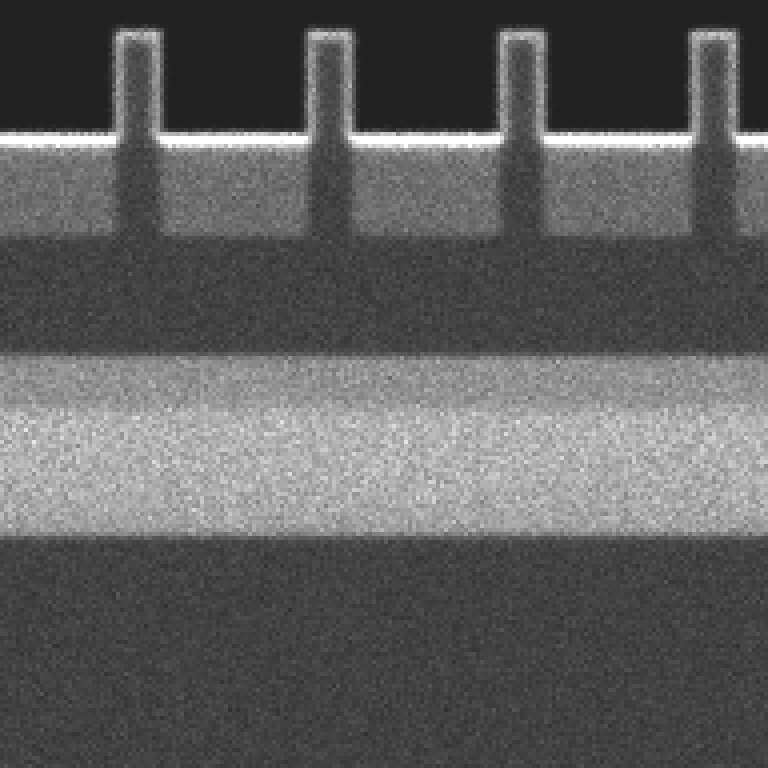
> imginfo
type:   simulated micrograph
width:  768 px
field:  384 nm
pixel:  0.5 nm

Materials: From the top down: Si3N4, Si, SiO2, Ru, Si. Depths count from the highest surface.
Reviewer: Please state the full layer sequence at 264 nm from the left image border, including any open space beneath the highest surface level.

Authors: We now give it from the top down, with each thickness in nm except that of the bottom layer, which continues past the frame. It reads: Si 162, SiO2 26, Ru 64, Si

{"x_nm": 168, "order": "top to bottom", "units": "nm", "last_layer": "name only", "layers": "Si 162, SiO2 26, Ru 64, Si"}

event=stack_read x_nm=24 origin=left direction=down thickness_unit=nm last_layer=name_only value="empty 52, Si3N4 50, Si 60, SiO2 26, Ru 64, Si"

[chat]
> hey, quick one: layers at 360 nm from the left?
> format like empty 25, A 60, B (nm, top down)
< Si 162, SiO2 26, Ru 64, Si